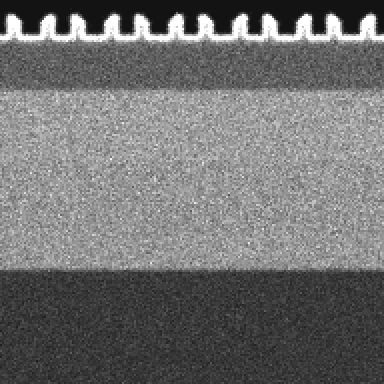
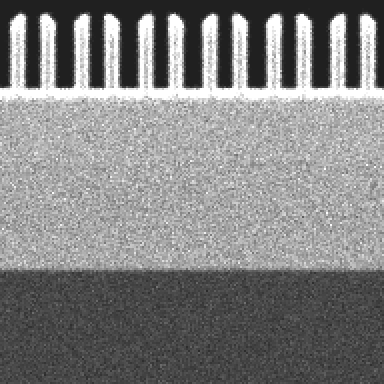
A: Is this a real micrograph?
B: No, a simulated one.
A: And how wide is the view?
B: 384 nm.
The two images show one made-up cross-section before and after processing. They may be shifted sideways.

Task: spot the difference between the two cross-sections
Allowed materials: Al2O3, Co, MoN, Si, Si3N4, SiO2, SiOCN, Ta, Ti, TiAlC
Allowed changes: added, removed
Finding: removed SiOCN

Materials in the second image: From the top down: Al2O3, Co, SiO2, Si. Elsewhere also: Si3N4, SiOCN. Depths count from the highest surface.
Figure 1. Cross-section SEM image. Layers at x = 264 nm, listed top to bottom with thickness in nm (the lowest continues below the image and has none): empty 74, Al2O3 72, Co 72, SiO2 36, Si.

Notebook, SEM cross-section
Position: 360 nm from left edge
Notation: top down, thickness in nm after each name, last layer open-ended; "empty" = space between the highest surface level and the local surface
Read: empty 74, Al2O3 72, Co 72, SiO2 36, Si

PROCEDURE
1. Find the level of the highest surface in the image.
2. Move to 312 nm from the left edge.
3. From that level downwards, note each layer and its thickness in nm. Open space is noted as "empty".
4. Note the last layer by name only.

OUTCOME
empty 74, Al2O3 72, Co 72, SiO2 36, Si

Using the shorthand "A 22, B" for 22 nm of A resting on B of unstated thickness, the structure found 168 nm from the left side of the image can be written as empty 74, Al2O3 72, Co 72, SiO2 36, Si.